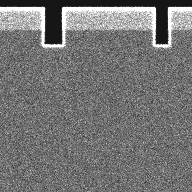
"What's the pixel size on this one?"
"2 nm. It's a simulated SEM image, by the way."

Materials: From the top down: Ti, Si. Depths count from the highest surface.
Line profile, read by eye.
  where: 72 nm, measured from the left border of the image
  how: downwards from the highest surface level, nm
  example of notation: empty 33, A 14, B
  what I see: Ti 44, Si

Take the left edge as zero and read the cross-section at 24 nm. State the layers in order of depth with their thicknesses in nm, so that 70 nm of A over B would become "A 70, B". Ti 44, Si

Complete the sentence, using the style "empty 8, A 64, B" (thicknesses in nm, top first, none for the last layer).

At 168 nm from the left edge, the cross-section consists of Ti 44, Si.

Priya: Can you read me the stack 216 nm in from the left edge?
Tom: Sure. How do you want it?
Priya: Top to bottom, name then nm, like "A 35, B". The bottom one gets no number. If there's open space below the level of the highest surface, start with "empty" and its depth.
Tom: Ti 44, Si